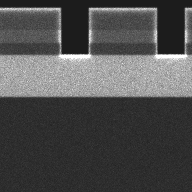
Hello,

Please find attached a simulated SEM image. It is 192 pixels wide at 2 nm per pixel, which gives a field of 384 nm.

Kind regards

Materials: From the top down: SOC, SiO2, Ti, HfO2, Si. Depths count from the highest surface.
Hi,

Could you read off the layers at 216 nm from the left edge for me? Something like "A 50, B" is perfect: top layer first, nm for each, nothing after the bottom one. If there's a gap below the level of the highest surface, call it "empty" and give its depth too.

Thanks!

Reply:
SOC 44, SiO2 26, Ti 24, HfO2 84, Si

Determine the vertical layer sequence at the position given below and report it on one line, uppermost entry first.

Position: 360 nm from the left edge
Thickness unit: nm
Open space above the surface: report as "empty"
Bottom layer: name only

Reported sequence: empty 94, HfO2 84, Si